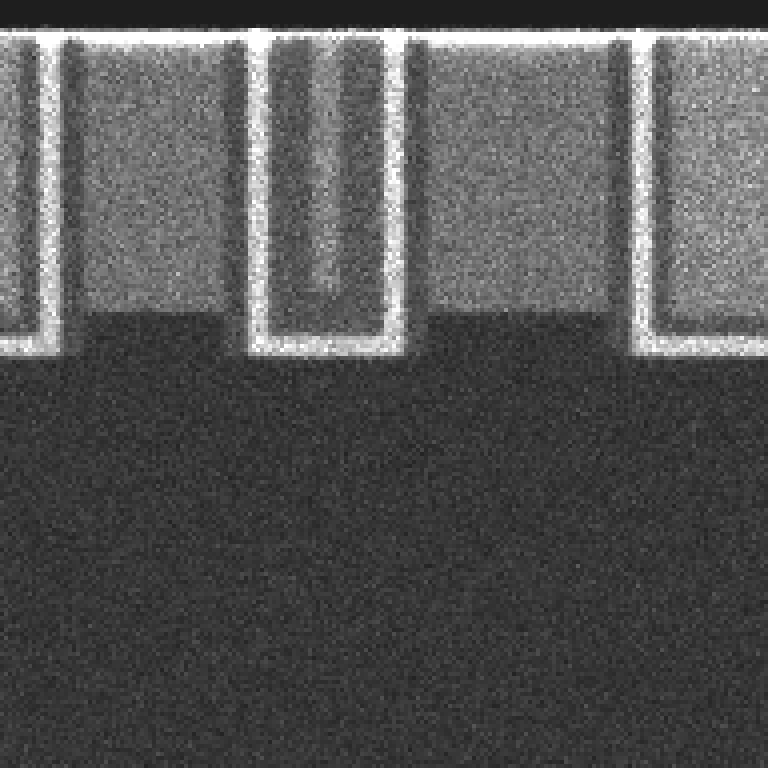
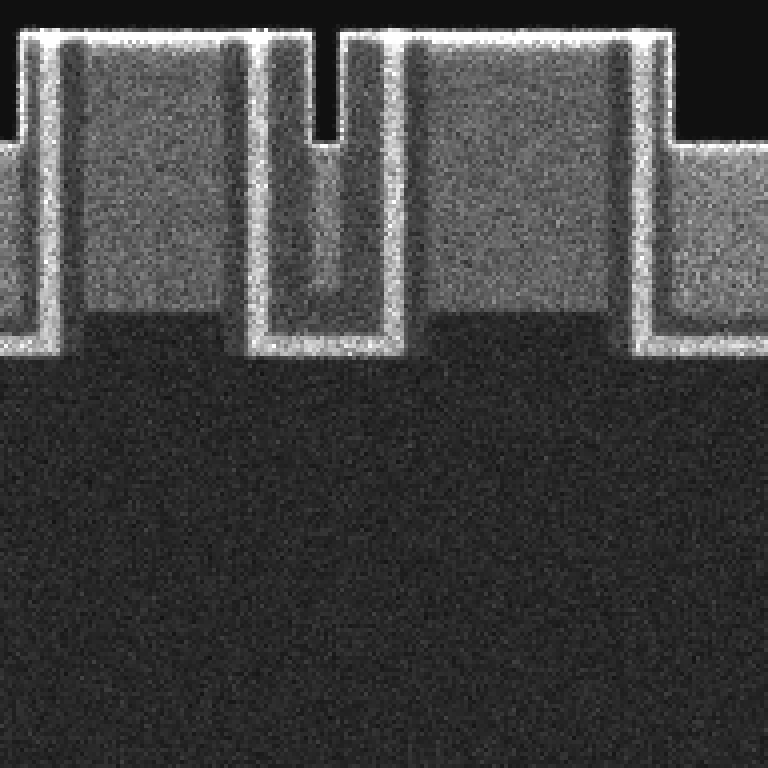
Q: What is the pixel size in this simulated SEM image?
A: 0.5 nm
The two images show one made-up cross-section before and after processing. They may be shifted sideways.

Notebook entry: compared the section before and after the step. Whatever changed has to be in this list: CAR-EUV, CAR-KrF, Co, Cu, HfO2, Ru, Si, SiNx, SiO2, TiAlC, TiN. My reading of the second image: Ru removed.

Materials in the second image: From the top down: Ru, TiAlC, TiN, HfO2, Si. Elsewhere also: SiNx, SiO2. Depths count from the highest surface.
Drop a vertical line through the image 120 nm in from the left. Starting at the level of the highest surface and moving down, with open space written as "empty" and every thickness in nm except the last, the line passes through SiNx 162, Si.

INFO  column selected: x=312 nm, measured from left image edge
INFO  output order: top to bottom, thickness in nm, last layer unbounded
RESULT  SiNx 162, Si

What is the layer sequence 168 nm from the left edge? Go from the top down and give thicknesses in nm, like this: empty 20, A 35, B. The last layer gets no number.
empty 56, Ru 74, TiAlC 10, TiN 12, HfO2 10, Si